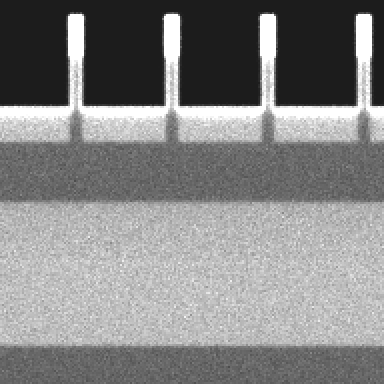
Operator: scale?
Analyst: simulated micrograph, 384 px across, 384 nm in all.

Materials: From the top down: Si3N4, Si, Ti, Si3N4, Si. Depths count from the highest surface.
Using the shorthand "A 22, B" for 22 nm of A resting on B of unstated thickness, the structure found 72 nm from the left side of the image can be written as Si 186, Ti 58, Si3N4 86, Si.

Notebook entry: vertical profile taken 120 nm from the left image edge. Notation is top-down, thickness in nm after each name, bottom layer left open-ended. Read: empty 92, Si3N4 34, Si 60, Ti 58, Si3N4 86, Si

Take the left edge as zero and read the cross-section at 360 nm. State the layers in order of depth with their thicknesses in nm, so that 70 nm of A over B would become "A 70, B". Si 186, Ti 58, Si3N4 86, Si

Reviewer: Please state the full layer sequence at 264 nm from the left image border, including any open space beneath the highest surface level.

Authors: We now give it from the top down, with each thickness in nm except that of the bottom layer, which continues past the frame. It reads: Si 186, Ti 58, Si3N4 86, Si